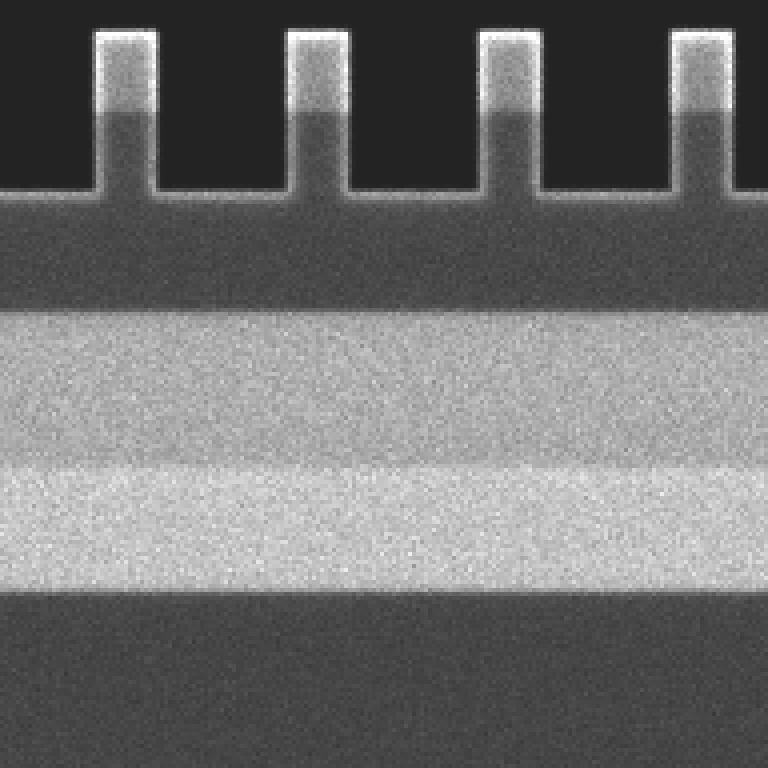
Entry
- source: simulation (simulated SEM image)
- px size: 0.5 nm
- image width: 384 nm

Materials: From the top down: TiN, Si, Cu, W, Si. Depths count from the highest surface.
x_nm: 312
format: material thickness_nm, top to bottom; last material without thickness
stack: empty 80, Si 60, Cu 78, W 62, Si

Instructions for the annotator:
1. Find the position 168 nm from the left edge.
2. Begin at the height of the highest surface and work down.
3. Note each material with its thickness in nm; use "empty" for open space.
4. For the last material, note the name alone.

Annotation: TiN 40, Si 100, Cu 78, W 62, Si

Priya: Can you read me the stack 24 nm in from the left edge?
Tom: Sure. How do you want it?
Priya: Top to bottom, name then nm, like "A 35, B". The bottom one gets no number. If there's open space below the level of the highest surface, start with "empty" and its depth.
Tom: empty 80, Si 60, Cu 78, W 62, Si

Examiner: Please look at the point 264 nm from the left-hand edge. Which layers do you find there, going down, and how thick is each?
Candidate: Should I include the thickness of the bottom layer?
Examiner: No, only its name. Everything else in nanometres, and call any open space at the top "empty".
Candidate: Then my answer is TiN 40, Si 100, Cu 78, W 62, Si